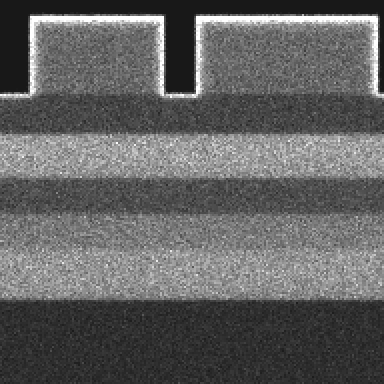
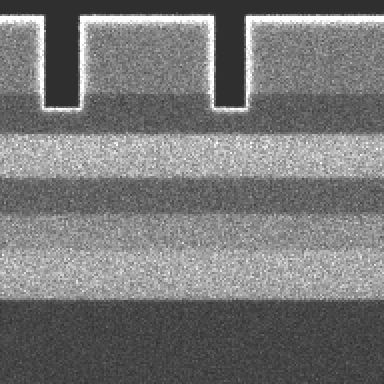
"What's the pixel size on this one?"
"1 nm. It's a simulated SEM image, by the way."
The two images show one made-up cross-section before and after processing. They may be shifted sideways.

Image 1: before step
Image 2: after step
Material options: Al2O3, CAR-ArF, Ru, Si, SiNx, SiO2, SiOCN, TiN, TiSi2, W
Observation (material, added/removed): SiNx, removed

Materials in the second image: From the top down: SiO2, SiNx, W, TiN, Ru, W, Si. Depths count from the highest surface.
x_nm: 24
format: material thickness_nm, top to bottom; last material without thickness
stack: SiO2 78, SiNx 40, W 44, TiN 36, Ru 36, W 50, Si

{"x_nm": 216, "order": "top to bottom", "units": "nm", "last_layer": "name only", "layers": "empty 92, SiNx 26, W 44, TiN 36, Ru 36, W 50, Si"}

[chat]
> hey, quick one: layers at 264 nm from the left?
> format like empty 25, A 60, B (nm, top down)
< SiO2 78, SiNx 40, W 44, TiN 36, Ru 36, W 50, Si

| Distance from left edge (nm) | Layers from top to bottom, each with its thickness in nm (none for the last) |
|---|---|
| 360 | SiO2 78, SiNx 40, W 44, TiN 36, Ru 36, W 50, Si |